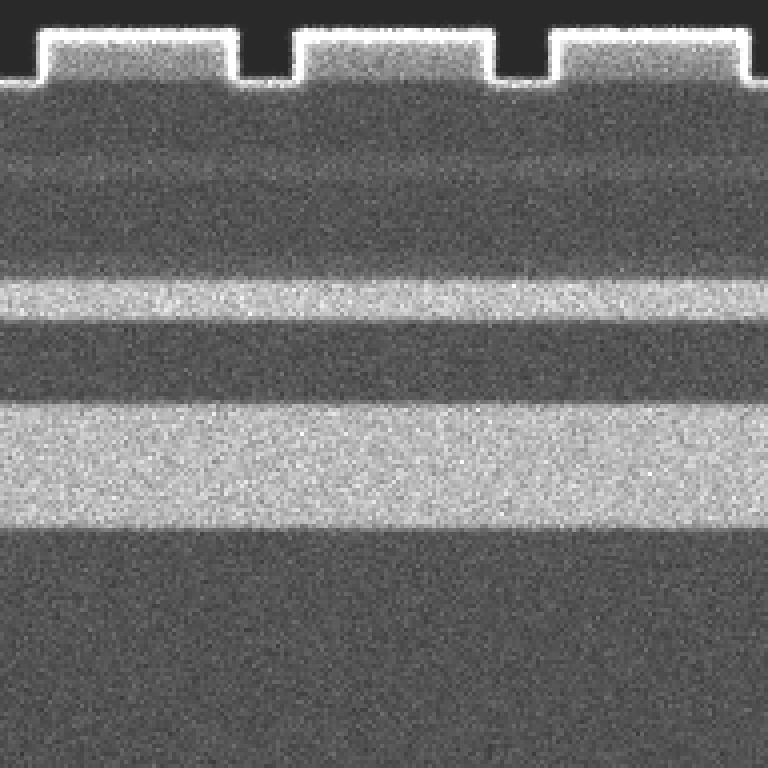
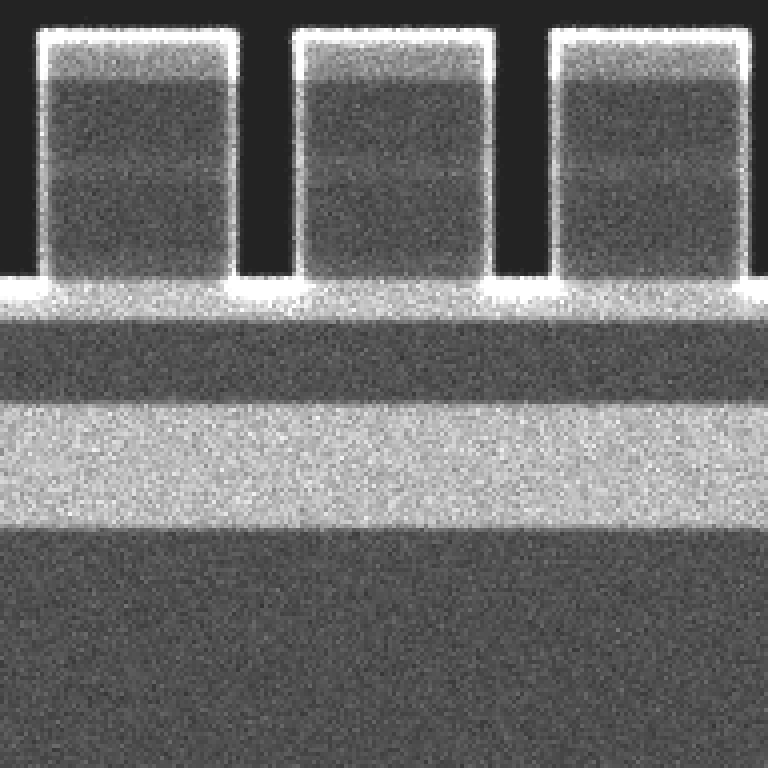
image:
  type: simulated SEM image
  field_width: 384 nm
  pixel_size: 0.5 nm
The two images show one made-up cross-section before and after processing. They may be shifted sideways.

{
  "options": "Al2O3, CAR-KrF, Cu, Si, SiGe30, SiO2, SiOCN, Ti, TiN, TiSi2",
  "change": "removed",
  "material": "Si and SiGe30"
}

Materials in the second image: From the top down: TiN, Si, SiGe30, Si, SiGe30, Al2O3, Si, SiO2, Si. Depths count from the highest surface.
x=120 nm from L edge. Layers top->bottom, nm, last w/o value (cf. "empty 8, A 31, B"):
empty 124, Al2O3 20, Si 42, SiO2 62, Si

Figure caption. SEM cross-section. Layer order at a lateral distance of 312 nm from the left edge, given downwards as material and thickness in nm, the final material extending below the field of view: TiN 24, Si 38, SiGe30 12, Si 38, SiGe30 12, Al2O3 20, Si 42, SiO2 62, Si